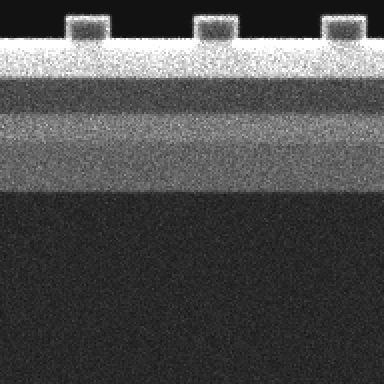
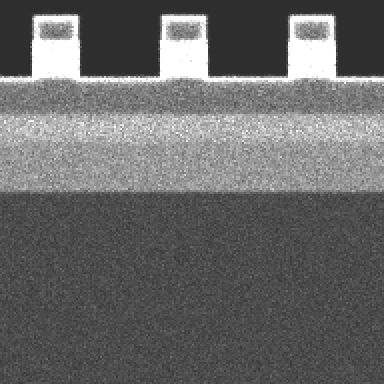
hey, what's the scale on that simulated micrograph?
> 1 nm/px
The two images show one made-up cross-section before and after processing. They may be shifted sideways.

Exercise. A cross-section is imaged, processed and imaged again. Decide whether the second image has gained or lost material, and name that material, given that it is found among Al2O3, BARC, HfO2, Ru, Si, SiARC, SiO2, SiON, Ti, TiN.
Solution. removed: HfO2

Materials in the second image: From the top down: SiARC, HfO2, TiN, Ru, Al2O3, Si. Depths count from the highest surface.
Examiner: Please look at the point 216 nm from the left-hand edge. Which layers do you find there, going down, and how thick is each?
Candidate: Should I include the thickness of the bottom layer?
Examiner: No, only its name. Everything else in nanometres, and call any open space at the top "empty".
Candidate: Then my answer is empty 62, TiN 36, Ru 28, Al2O3 50, Si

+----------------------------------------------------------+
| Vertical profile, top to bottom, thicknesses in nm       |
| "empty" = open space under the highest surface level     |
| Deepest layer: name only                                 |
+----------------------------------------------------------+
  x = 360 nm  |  empty 62, TiN 36, Ru 28, Al2O3 50, Si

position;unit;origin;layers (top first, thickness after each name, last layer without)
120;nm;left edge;empty 62, TiN 36, Ru 28, Al2O3 50, Si